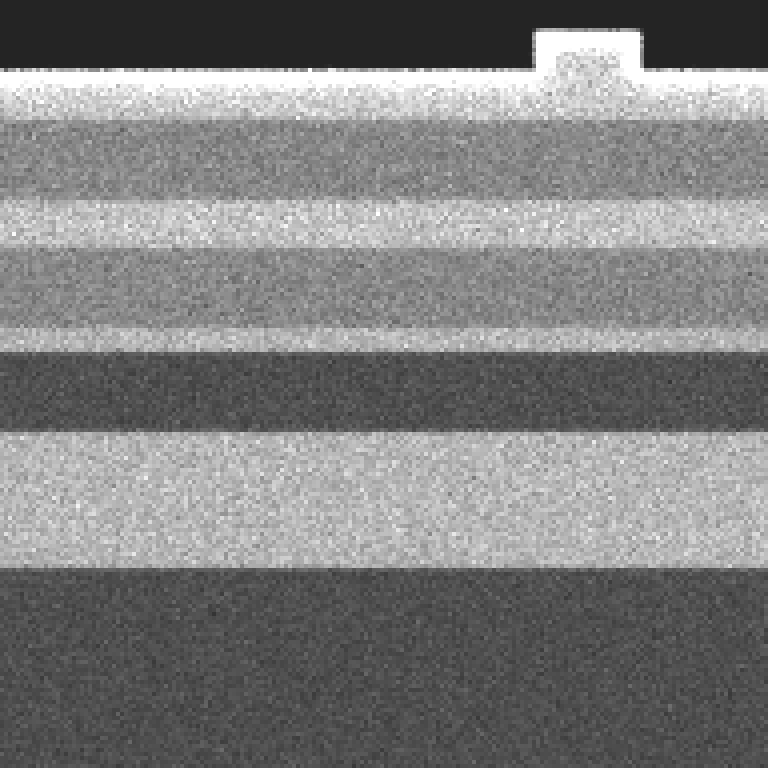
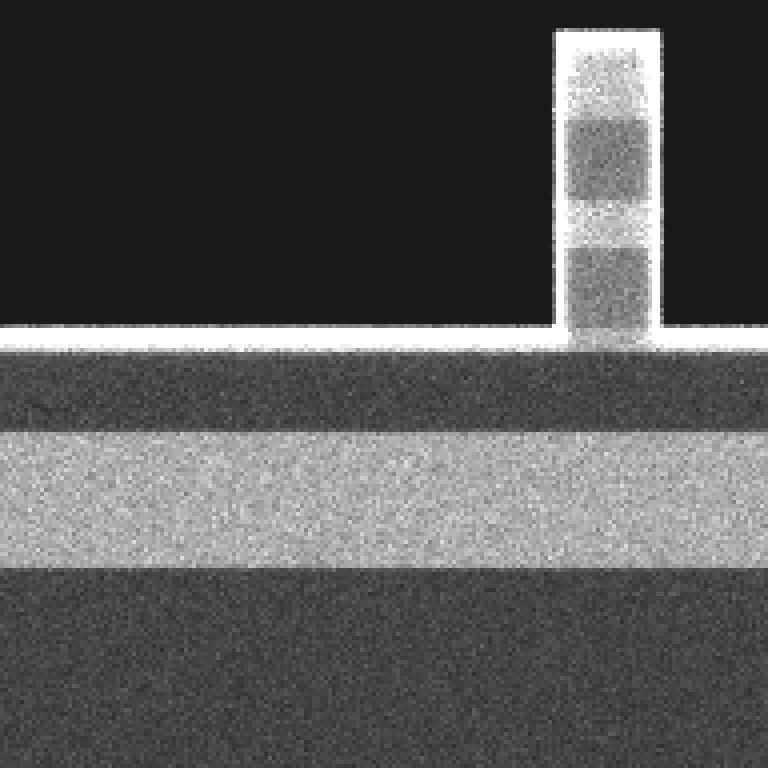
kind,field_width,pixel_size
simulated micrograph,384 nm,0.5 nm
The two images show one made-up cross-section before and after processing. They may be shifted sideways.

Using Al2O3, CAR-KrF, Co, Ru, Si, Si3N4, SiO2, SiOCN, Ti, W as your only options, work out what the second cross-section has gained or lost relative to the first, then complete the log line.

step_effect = removed Co and Si3N4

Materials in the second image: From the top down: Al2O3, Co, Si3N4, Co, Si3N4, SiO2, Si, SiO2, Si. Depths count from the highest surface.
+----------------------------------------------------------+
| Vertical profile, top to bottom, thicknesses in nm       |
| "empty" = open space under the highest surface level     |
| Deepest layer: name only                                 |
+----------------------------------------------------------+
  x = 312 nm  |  Al2O3 20, Co 24, Si3N4 40, Co 24, Si3N4 40, SiO2 12, Si 40, SiO2 68, Si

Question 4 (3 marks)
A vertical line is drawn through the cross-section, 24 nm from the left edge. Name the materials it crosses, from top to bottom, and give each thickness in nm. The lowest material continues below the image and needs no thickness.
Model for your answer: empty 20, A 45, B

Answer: empty 148, SiO2 12, Si 40, SiO2 68, Si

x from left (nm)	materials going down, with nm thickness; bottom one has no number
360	empty 148, SiO2 12, Si 40, SiO2 68, Si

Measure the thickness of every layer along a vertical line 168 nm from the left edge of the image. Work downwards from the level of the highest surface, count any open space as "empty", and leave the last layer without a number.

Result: empty 148, SiO2 12, Si 40, SiO2 68, Si